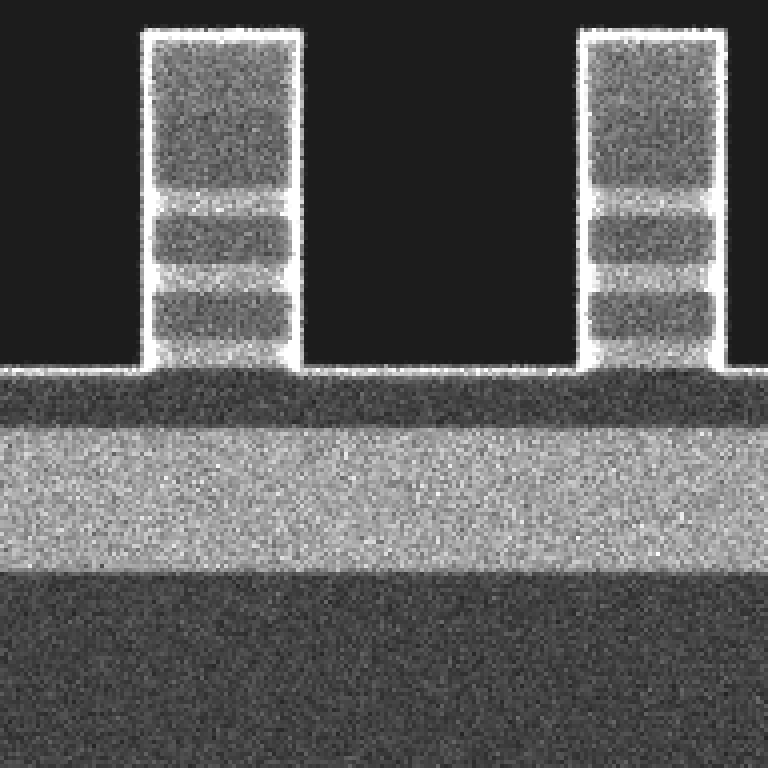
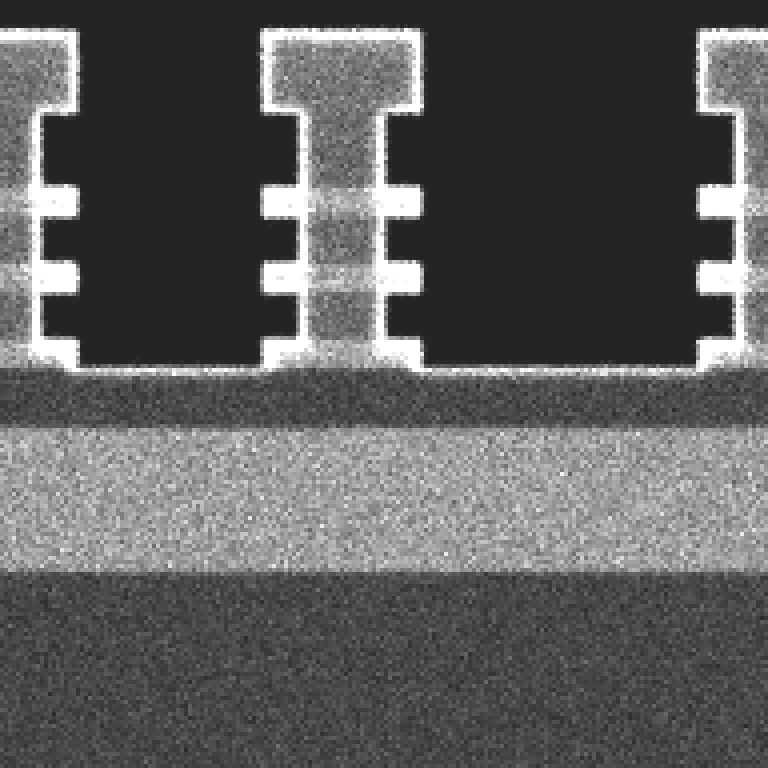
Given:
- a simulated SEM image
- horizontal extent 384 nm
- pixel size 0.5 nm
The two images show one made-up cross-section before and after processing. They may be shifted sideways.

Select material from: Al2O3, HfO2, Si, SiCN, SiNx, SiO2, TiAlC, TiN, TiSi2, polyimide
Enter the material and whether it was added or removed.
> SiNx / removed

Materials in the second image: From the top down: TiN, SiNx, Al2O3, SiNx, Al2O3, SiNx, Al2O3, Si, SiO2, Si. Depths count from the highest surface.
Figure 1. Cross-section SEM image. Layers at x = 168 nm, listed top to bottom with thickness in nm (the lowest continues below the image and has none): TiN 40, SiNx 38, Al2O3 14, SiNx 24, Al2O3 14, SiNx 24, Al2O3 14, Si 30, SiO2 72, Si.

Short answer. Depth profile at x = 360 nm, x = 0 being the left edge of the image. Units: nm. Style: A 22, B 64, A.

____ TiN 40, empty 38, Al2O3 14, empty 24, Al2O3 14, empty 24, Al2O3 14, Si 30, SiO2 72, Si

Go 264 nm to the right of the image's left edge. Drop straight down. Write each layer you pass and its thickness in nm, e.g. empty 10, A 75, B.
empty 168, Si 30, SiO2 72, Si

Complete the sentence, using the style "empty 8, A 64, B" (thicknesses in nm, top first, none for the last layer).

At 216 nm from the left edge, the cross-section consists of empty 168, Si 30, SiO2 72, Si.